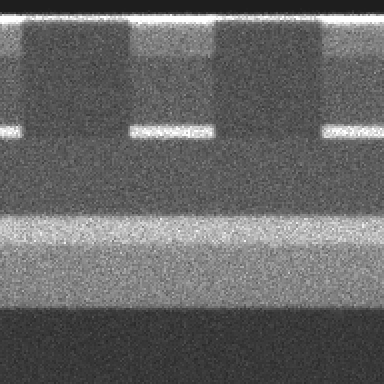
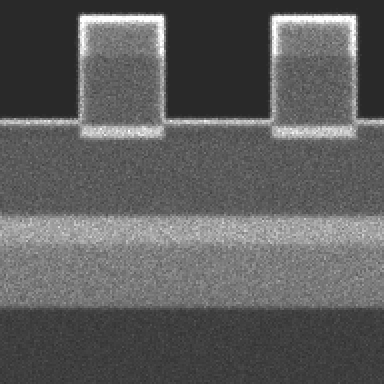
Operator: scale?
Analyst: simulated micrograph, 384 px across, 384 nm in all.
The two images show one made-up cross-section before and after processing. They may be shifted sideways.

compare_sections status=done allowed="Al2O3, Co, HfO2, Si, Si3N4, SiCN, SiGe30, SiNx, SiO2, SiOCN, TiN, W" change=removed material="SiNx"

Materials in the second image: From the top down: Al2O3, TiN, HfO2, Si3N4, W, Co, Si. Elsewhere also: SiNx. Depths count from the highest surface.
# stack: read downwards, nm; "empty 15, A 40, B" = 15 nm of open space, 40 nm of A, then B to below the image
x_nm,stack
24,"empty 104, SiNx 18, Si3N4 78, W 28, Co 64, Si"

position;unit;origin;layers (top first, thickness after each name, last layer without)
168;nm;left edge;empty 104, SiNx 18, Si3N4 78, W 28, Co 64, Si